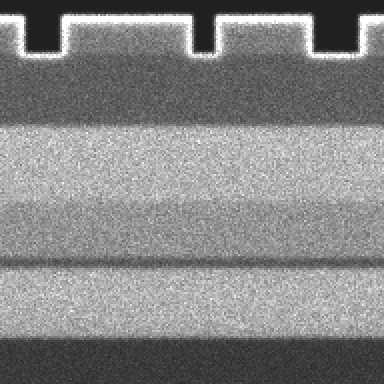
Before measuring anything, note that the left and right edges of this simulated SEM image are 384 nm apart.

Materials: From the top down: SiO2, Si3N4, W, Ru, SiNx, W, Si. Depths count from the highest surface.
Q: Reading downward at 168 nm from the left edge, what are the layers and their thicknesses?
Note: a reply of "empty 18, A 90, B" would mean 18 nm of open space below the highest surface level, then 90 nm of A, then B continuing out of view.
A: SiO2 38, Si3N4 72, W 76, Ru 56, SiNx 10, W 70, Si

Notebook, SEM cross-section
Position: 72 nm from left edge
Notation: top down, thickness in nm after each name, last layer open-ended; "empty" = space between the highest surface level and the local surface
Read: SiO2 38, Si3N4 72, W 76, Ru 56, SiNx 10, W 70, Si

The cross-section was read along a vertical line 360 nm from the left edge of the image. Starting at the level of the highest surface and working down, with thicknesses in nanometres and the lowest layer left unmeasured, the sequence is SiO2 38, Si3N4 72, W 76, Ru 56, SiNx 10, W 70, Si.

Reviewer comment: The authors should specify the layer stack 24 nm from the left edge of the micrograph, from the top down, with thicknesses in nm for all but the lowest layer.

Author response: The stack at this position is empty 38, Si3N4 72, W 76, Ru 56, SiNx 10, W 70, Si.